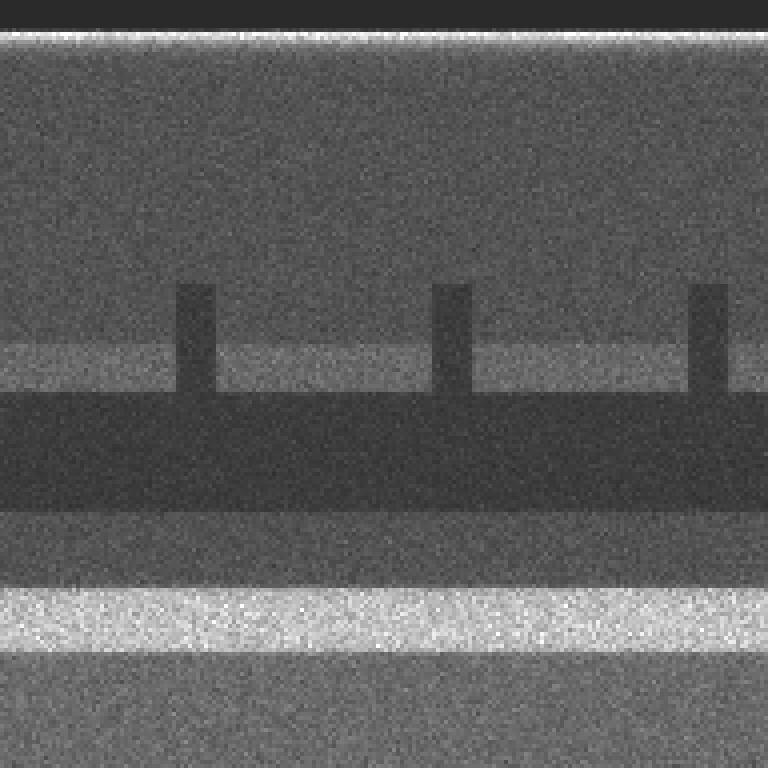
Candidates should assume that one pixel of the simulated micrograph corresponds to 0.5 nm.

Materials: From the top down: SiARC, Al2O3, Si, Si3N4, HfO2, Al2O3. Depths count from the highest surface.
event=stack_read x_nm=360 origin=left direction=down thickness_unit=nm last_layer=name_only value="SiARC 126, Si 114, Si3N4 38, HfO2 32, Al2O3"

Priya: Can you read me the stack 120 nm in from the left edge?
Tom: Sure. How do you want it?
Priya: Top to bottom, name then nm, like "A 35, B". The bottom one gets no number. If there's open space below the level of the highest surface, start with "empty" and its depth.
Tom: SiARC 156, Al2O3 24, Si 60, Si3N4 38, HfO2 32, Al2O3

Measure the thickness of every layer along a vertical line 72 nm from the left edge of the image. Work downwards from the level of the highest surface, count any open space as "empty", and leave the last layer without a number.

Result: SiARC 156, Al2O3 24, Si 60, Si3N4 38, HfO2 32, Al2O3